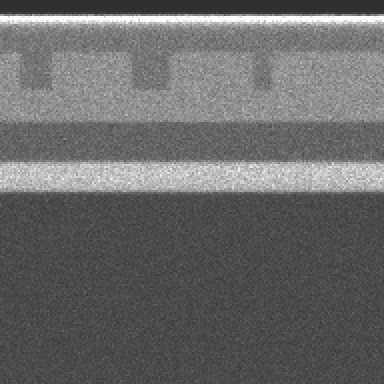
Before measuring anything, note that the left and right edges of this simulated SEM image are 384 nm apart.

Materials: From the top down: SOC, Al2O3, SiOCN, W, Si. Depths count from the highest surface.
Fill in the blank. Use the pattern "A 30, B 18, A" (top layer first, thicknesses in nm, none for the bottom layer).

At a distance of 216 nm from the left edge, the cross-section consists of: SOC 36, Al2O3 70, SiOCN 40, W 30, Si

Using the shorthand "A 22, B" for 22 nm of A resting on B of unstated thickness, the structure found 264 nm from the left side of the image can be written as SOC 74, Al2O3 32, SiOCN 40, W 30, Si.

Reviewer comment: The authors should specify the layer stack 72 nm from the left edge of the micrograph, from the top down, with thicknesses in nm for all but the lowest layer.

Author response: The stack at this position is SOC 36, Al2O3 70, SiOCN 40, W 30, Si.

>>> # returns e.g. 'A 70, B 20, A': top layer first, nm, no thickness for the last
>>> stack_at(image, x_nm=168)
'SOC 74, Al2O3 32, SiOCN 40, W 30, Si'